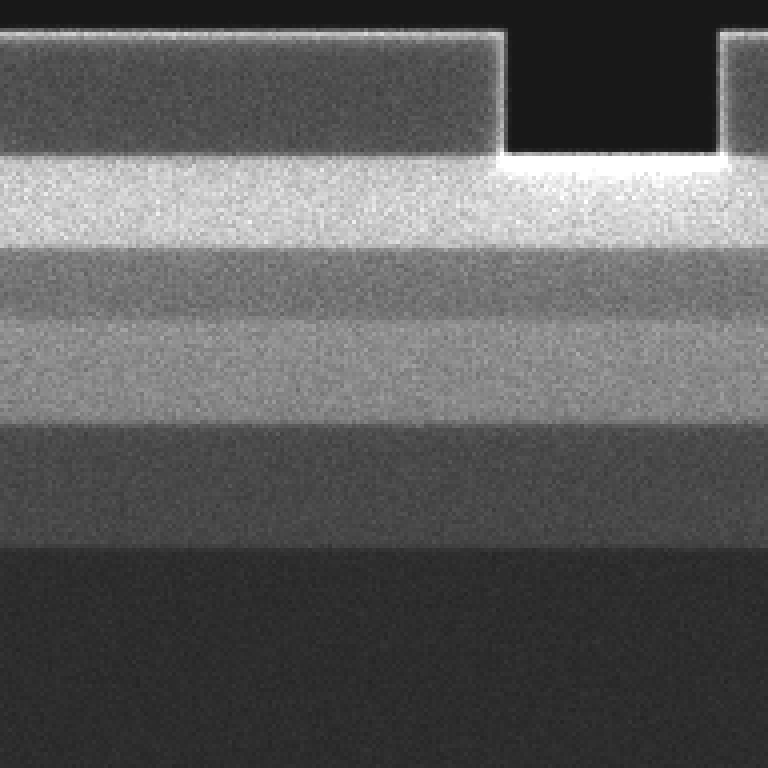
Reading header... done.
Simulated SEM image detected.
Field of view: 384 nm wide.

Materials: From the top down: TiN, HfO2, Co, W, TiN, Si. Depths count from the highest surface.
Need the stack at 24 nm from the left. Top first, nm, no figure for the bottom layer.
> TiN 62, HfO2 46, Co 36, W 52, TiN 62, Si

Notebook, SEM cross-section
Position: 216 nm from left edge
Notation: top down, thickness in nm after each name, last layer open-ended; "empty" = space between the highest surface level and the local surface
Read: TiN 62, HfO2 46, Co 36, W 52, TiN 62, Si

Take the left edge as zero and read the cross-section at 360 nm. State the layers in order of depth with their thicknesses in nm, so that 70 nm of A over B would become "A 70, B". TiN 62, HfO2 46, Co 36, W 52, TiN 62, Si